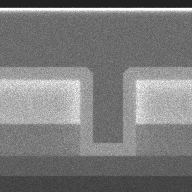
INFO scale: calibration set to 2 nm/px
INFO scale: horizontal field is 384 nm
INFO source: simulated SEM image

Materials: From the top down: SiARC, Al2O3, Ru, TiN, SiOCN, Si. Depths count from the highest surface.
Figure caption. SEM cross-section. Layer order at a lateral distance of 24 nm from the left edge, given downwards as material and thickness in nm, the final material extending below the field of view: SiARC 118, Al2O3 26, Ru 88, TiN 64, SiOCN 40, Si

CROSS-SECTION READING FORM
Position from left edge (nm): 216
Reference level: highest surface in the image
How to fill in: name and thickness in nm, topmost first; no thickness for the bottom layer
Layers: SiARC 270, Al2O3 26, SiOCN 40, Si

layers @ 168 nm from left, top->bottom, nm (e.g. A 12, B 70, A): SiARC 118, Al2O3 178, SiOCN 40, Si